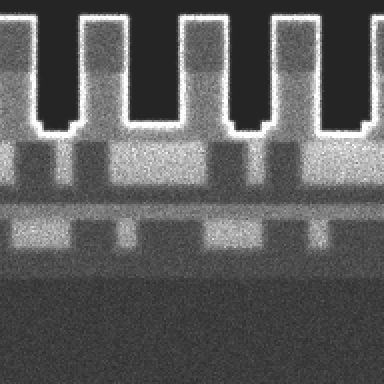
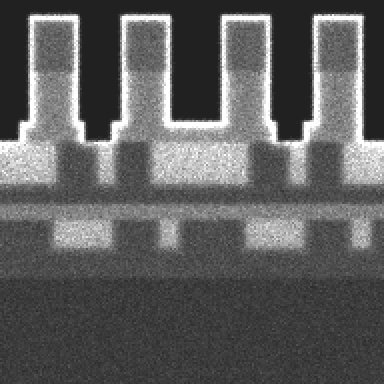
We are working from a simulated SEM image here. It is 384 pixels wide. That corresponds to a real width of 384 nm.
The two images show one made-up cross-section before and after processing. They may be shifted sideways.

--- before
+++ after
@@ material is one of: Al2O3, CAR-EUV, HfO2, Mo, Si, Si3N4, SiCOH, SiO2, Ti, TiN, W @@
Al2O3 removed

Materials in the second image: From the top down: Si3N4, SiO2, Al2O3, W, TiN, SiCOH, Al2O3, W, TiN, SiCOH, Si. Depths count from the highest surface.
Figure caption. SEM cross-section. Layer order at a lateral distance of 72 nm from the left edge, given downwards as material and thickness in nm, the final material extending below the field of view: Si3N4 56, SiO2 60, Al2O3 10, SiCOH 62, Al2O3 16, W 28, TiN 6, SiCOH 24, Si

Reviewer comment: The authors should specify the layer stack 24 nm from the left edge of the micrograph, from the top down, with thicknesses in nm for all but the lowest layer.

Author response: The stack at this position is empty 106, SiO2 10, Al2O3 10, W 42, TiN 6, SiCOH 14, Al2O3 16, SiCOH 58, Si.